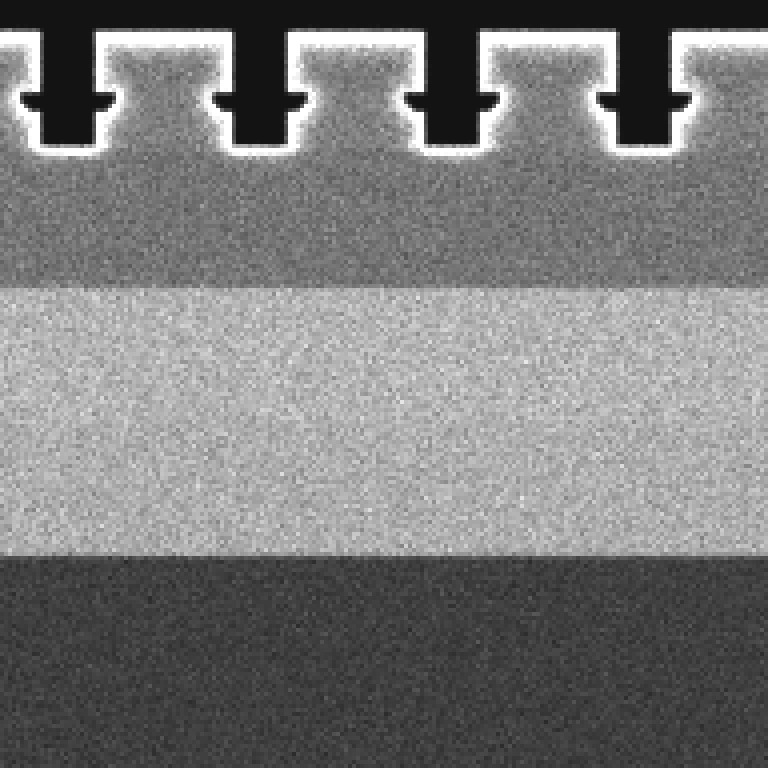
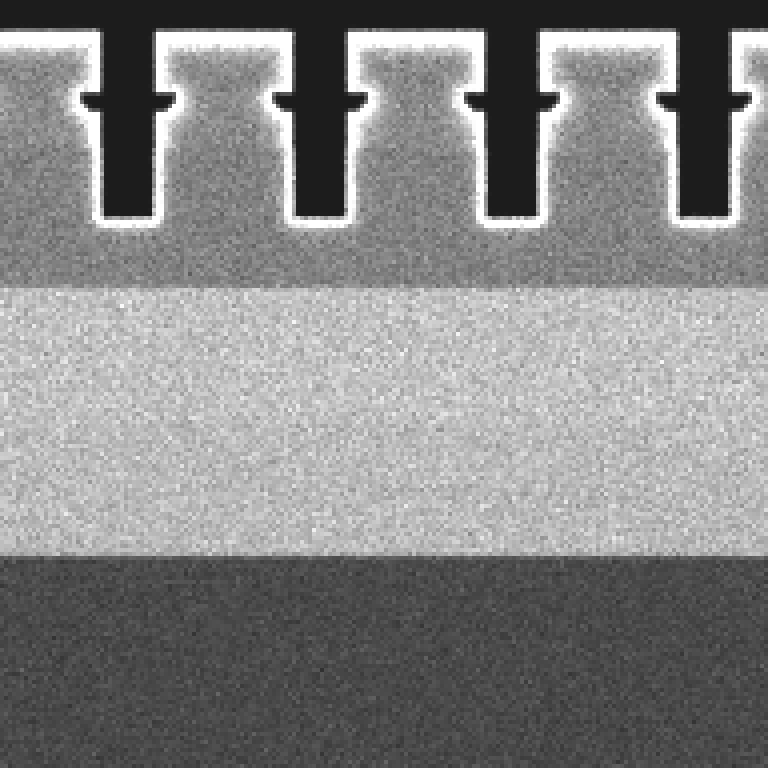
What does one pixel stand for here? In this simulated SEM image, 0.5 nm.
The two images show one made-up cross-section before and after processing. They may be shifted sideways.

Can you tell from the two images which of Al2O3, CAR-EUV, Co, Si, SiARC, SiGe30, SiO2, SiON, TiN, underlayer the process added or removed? Yes, it removed TiN.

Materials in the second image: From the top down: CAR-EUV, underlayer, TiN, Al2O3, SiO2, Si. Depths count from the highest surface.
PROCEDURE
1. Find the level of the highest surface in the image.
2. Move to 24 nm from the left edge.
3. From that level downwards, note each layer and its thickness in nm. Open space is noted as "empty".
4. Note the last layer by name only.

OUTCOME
CAR-EUV 30, underlayer 28, TiN 70, Al2O3 68, SiO2 66, Si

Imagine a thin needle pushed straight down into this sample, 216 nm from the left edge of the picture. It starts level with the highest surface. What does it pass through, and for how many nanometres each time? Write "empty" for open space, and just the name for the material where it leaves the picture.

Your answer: CAR-EUV 30, underlayer 28, TiN 70, Al2O3 68, SiO2 66, Si